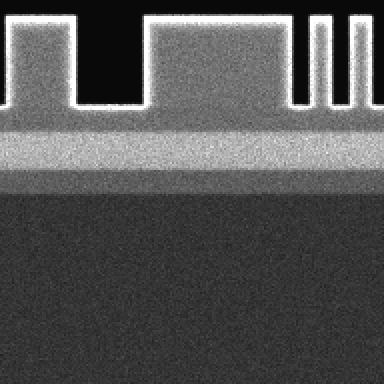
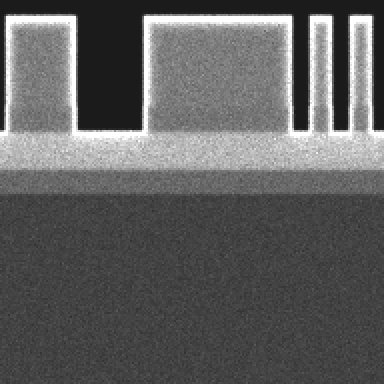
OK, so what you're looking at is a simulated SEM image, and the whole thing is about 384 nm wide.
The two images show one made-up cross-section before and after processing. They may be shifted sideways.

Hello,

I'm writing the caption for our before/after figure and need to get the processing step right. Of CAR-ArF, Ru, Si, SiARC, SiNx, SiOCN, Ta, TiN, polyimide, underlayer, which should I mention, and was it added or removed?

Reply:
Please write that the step removed TiN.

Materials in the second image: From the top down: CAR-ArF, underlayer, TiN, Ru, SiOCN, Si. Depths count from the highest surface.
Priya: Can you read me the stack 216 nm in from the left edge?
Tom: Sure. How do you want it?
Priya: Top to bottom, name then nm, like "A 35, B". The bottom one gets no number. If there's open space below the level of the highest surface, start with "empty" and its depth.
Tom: CAR-ArF 66, underlayer 24, TiN 26, Ru 38, SiOCN 24, Si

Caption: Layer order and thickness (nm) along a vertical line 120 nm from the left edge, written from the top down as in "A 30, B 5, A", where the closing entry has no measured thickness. empty 116, Ru 38, SiOCN 24, Si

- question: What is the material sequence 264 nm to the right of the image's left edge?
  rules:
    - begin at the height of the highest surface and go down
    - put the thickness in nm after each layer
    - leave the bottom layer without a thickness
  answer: CAR-ArF 66, underlayer 24, TiN 26, Ru 38, SiOCN 24, Si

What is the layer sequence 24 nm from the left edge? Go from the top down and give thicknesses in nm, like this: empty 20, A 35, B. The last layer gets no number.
CAR-ArF 66, underlayer 24, TiN 26, Ru 38, SiOCN 24, Si